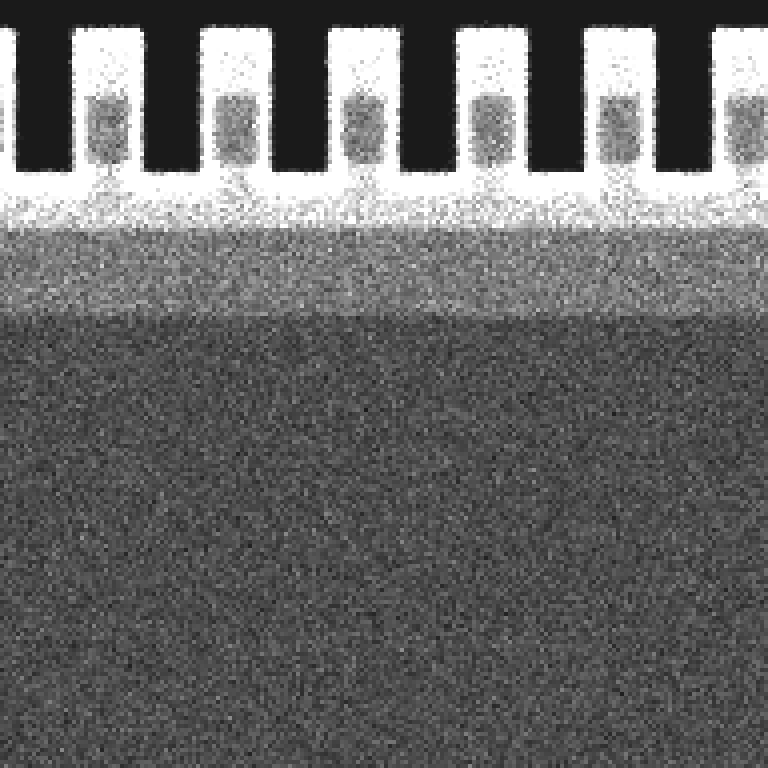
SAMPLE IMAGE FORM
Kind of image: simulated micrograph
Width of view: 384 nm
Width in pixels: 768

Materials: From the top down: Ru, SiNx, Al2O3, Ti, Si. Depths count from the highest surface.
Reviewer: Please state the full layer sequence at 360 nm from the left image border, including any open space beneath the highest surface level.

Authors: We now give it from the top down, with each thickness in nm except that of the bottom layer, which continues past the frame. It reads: Ru 32, SiNx 34, Al2O3 32, Ti 44, Si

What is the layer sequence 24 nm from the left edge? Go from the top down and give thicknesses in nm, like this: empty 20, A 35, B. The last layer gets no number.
empty 72, Al2O3 26, Ti 44, Si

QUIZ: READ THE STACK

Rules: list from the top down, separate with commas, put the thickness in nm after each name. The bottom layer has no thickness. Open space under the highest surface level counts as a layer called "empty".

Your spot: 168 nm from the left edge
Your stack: Ru 32, SiNx 34, Al2O3 32, Ti 44, Si